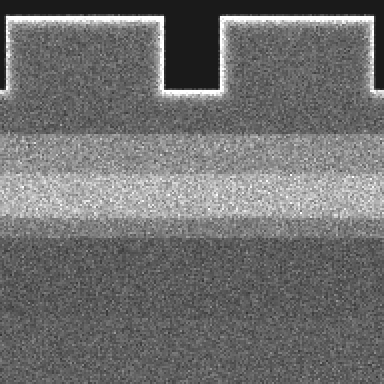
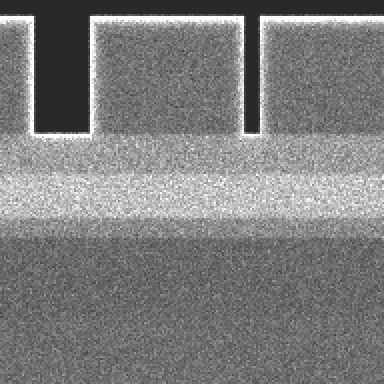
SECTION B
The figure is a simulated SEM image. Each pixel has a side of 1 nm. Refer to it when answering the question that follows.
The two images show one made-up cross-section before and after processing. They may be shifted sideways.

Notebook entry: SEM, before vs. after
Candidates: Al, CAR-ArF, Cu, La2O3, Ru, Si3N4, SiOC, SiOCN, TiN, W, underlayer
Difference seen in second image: underlayer removed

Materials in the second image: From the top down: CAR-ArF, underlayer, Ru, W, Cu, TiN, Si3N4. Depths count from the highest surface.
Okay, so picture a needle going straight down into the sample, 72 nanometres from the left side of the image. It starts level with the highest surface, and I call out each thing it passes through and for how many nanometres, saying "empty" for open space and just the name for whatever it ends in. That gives empty 118, Ru 40, W 44, Cu 20, TiN 80, Si3N4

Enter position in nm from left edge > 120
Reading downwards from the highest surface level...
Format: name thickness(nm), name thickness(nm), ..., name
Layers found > CAR-ArF 74, underlayer 44, Ru 40, W 44, Cu 20, TiN 80, Si3N4